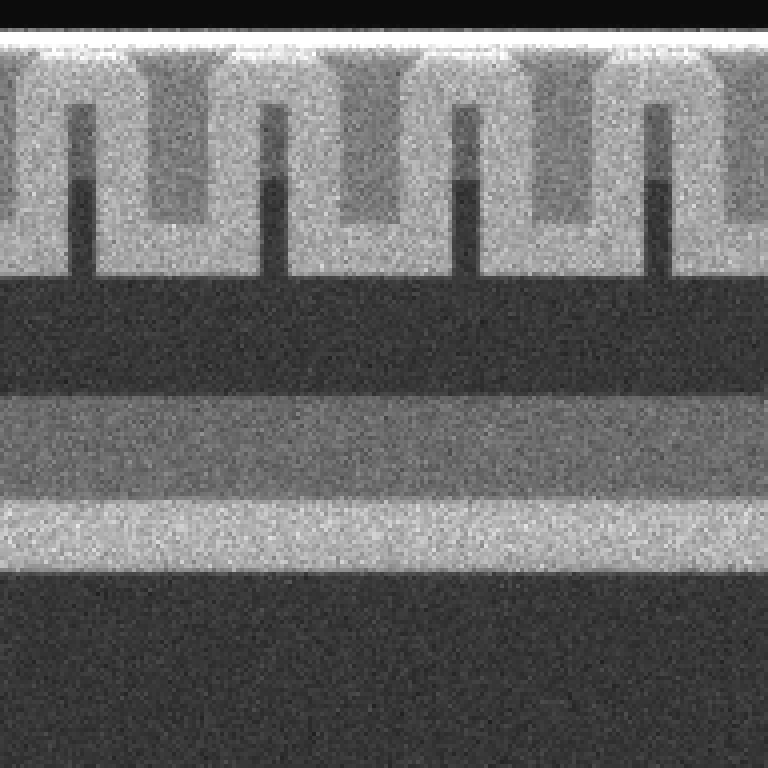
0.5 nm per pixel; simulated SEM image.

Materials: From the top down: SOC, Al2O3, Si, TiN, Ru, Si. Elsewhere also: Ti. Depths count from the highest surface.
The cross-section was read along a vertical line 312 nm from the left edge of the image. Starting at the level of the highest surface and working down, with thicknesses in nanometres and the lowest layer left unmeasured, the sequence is SOC 10, Al2O3 112, Si 60, TiN 52, Ru 36, Si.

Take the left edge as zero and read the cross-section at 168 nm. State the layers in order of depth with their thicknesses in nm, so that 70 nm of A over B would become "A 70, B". SOC 22, Al2O3 100, Si 60, TiN 52, Ru 36, Si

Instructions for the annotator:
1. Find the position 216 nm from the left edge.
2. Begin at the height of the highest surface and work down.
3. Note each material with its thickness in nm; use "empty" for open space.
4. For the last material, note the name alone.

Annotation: SOC 10, Al2O3 112, Si 60, TiN 52, Ru 36, Si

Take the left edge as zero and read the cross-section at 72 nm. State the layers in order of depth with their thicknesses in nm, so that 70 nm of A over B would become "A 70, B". SOC 22, Al2O3 100, Si 60, TiN 52, Ru 36, Si